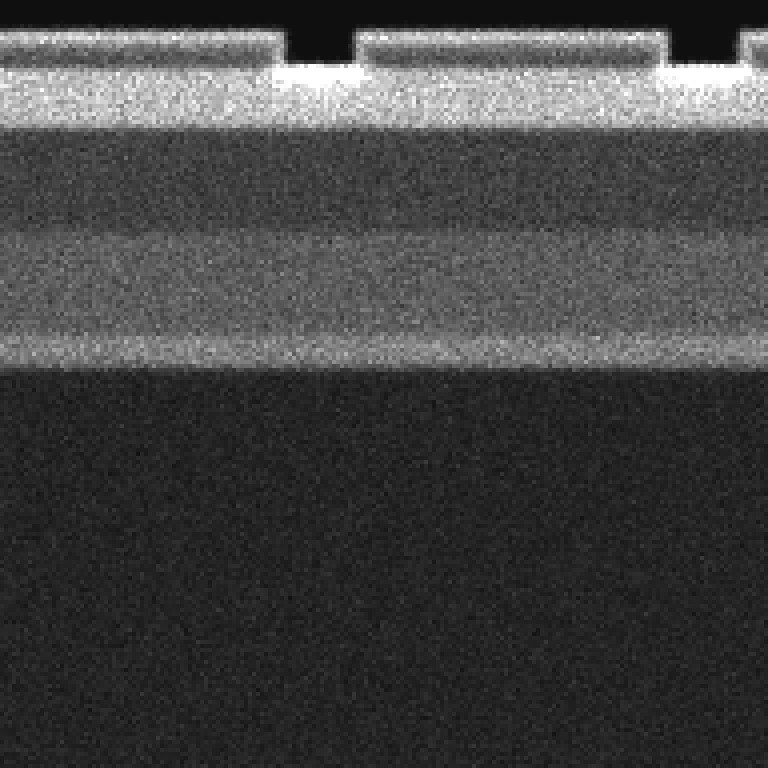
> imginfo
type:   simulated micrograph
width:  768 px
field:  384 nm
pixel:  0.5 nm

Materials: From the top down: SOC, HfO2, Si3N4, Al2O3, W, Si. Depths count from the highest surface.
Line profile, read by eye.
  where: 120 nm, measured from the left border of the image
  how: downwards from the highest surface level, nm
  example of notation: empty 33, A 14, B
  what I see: SOC 18, HfO2 30, Si3N4 52, Al2O3 52, W 16, Si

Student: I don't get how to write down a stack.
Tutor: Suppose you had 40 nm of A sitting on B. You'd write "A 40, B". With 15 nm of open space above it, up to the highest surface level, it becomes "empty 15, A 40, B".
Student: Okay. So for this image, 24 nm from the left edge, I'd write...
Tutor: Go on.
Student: SOC 18, HfO2 30, Si3N4 52, Al2O3 52, W 16, Si